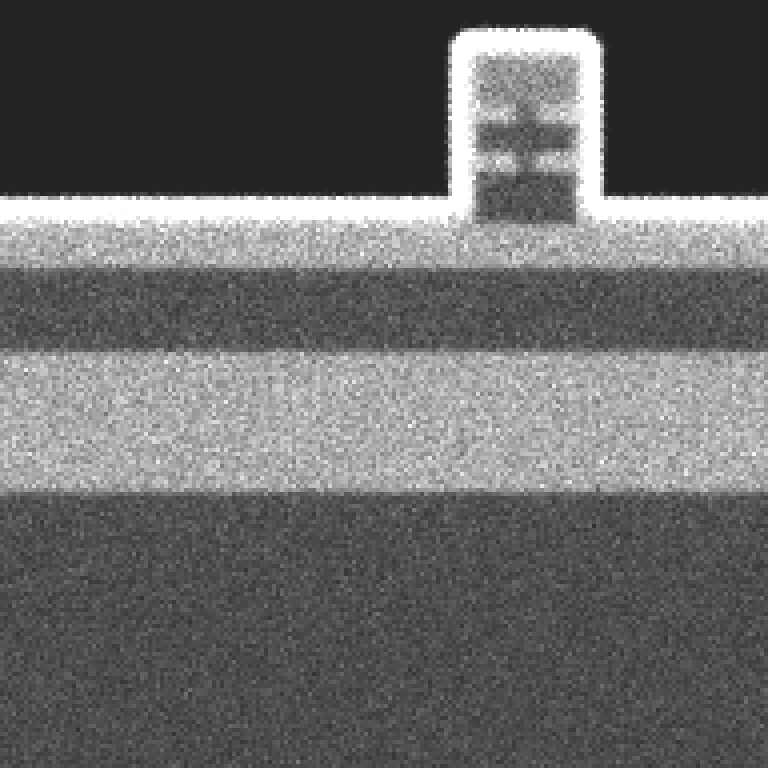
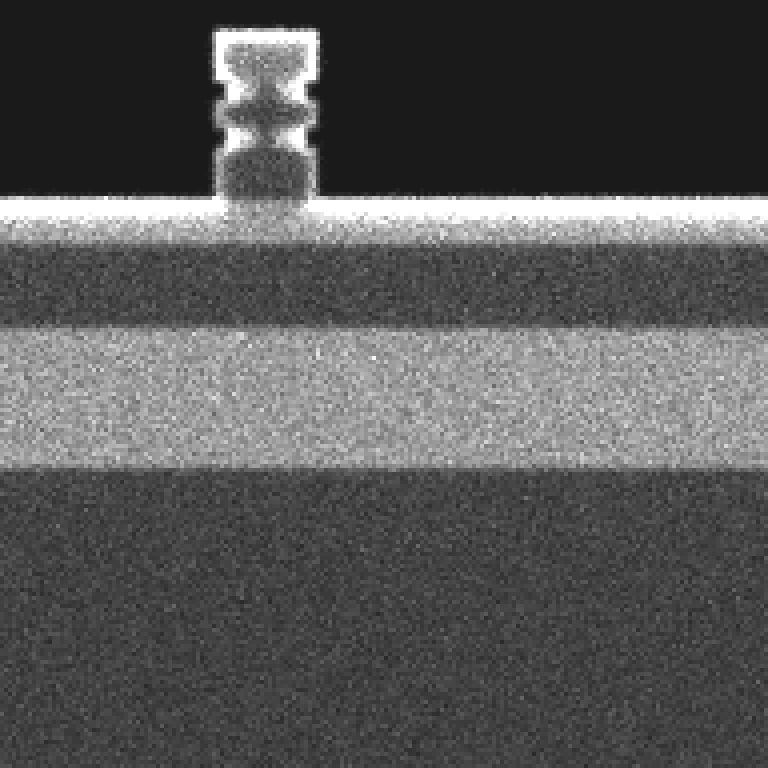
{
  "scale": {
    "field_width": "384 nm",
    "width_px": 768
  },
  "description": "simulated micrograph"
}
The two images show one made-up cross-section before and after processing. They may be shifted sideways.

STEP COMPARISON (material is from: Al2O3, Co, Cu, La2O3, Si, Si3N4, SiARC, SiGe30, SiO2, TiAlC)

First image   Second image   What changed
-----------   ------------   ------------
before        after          Al2O3, removed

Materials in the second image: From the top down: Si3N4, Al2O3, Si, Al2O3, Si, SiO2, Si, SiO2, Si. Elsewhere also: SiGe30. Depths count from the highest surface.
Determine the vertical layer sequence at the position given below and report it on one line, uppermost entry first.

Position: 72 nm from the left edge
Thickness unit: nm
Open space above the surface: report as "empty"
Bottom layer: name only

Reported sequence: empty 84, SiO2 22, Si 42, SiO2 70, Si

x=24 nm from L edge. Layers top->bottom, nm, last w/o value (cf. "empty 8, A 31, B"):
empty 84, SiO2 22, Si 42, SiO2 70, Si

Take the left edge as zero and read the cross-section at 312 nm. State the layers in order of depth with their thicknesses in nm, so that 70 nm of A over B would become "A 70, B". empty 84, SiO2 22, Si 42, SiO2 70, Si